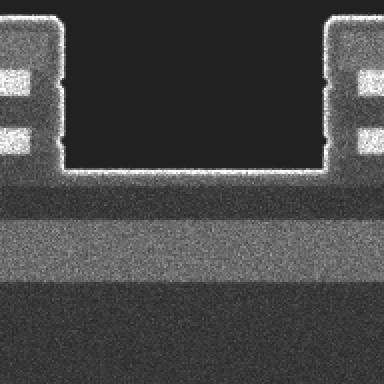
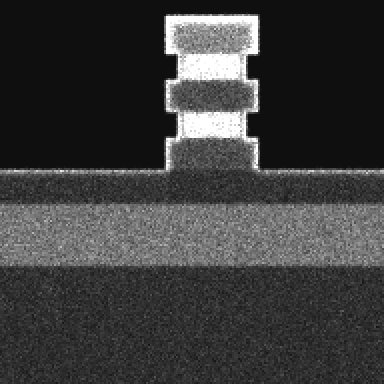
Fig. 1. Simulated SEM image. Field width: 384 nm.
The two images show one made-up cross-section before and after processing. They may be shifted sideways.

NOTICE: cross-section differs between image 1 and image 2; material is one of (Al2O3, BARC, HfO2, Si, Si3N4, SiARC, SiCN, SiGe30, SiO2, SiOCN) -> removed: Si3N4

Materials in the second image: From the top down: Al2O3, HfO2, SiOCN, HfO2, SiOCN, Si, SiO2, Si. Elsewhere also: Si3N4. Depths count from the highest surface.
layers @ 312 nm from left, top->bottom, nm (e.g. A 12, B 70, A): empty 154, Si 34, SiO2 62, Si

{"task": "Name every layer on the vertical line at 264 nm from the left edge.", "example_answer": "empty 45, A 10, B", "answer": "empty 154, Si 34, SiO2 62, Si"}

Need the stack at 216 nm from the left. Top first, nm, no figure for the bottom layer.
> Al2O3 38, HfO2 26, SiOCN 32, HfO2 26, SiOCN 32, Si 34, SiO2 62, Si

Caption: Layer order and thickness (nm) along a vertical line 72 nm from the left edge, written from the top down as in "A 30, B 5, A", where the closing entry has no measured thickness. empty 154, Si 34, SiO2 62, Si